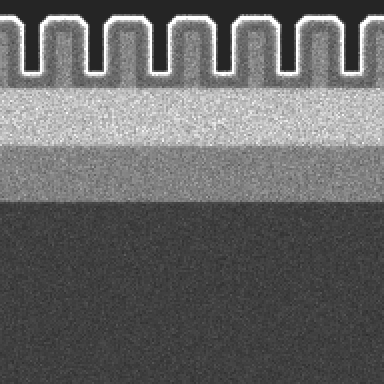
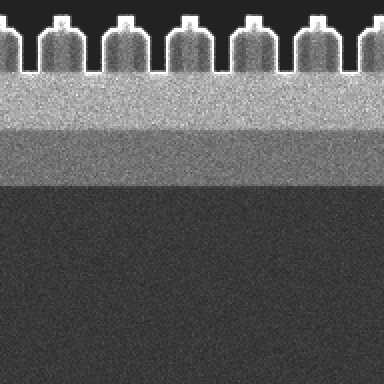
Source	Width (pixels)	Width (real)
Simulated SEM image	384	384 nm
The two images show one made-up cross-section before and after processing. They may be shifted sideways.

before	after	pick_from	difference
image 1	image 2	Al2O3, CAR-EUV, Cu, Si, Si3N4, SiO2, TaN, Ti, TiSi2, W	Si3N4 removed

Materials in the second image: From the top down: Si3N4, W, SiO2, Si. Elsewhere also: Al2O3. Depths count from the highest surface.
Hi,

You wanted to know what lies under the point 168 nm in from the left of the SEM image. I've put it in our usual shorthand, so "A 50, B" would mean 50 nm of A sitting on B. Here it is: empty 18, Si3N4 38, W 58, SiO2 56, Si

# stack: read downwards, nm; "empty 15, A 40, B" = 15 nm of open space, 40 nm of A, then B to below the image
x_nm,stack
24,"empty 56, W 58, SiO2 56, Si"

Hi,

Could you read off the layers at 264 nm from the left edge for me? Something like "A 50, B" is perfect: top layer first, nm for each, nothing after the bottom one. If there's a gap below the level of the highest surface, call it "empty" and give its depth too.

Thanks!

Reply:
empty 12, Si3N4 44, W 58, SiO2 56, Si